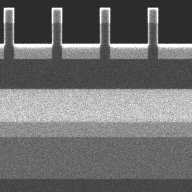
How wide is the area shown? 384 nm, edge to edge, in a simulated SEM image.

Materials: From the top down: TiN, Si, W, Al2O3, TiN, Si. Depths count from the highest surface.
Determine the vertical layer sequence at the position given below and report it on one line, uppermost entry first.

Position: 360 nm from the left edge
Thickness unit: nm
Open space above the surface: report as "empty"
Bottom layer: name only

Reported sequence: empty 72, Al2O3 30, Si 60, W 66, Al2O3 30, TiN 84, Si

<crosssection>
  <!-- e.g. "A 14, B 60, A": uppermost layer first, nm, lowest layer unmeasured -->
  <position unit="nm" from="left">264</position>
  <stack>empty 72, Al2O3 30, Si 60, W 66, Al2O3 30, TiN 84, Si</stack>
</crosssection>